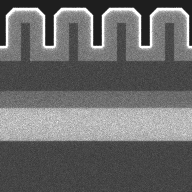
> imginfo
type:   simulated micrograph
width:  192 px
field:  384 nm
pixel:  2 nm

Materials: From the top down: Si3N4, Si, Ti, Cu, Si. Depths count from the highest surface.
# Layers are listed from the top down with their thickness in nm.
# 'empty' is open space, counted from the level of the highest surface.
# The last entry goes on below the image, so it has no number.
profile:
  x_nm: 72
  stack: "Si3N4 106, Si 60, Ti 34, Cu 66, Si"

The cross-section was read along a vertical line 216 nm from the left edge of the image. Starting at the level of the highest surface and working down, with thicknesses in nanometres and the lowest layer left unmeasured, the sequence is empty 2, Si3N4 104, Si 60, Ti 34, Cu 66, Si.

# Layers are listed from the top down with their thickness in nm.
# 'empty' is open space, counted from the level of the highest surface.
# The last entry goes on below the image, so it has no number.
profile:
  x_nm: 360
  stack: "Si3N4 106, Si 60, Ti 34, Cu 66, Si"